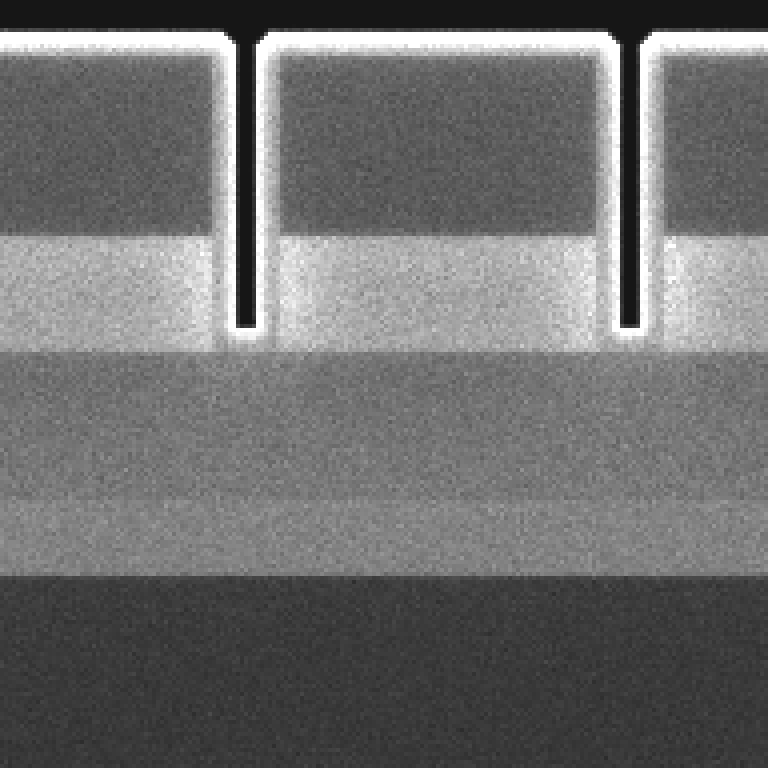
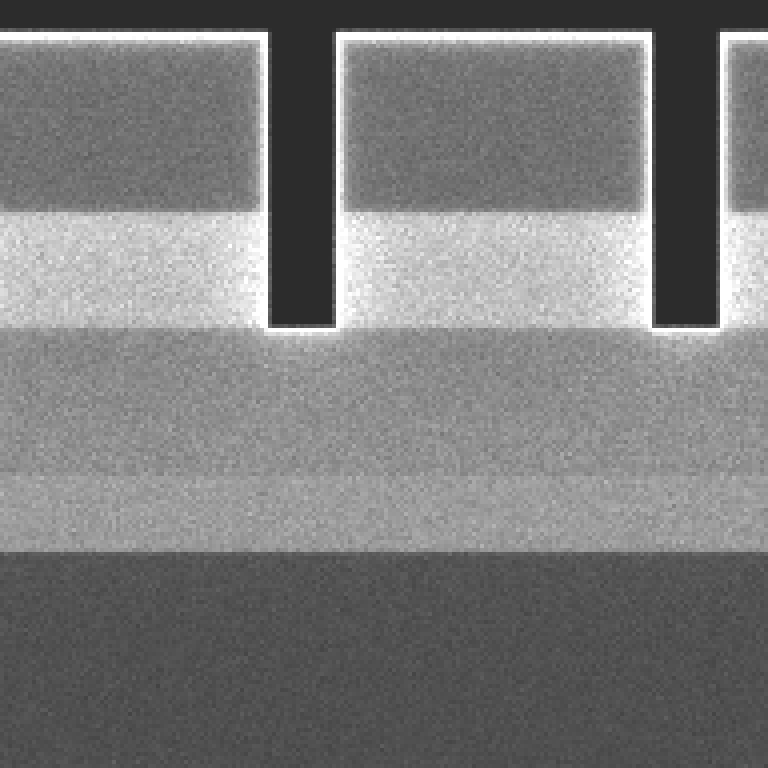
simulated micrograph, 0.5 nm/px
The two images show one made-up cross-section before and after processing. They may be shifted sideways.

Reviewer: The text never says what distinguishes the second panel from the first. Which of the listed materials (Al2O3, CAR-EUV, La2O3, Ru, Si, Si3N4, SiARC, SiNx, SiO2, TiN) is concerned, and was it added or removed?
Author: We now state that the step removed Al2O3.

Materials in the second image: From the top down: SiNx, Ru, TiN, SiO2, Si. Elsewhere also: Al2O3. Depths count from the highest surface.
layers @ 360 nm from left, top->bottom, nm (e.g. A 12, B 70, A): SiNx 90, Ru 58, TiN 74, SiO2 38, Si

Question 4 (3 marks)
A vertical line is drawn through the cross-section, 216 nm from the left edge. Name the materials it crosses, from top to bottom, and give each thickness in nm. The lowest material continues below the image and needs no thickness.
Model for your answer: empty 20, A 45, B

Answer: SiNx 90, Ru 58, TiN 74, SiO2 38, Si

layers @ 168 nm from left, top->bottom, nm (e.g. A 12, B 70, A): SiNx 90, Ru 58, TiN 74, SiO2 38, Si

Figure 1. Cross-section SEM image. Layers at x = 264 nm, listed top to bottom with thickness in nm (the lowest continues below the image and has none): SiNx 90, Ru 58, TiN 74, SiO2 38, Si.